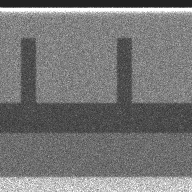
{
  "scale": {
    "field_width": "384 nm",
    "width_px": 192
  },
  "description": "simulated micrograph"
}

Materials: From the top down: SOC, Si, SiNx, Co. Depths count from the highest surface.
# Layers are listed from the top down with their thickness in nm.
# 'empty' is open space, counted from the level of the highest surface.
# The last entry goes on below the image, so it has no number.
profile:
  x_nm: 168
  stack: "SOC 190, Si 60, SiNx 88, Co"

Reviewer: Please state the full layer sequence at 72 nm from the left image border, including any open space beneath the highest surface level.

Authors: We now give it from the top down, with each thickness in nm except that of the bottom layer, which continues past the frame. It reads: SOC 190, Si 60, SiNx 88, Co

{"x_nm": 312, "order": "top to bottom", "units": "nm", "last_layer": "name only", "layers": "SOC 190, Si 60, SiNx 88, Co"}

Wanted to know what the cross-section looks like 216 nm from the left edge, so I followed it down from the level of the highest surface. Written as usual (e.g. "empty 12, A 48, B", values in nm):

SOC 190, Si 60, SiNx 88, Co